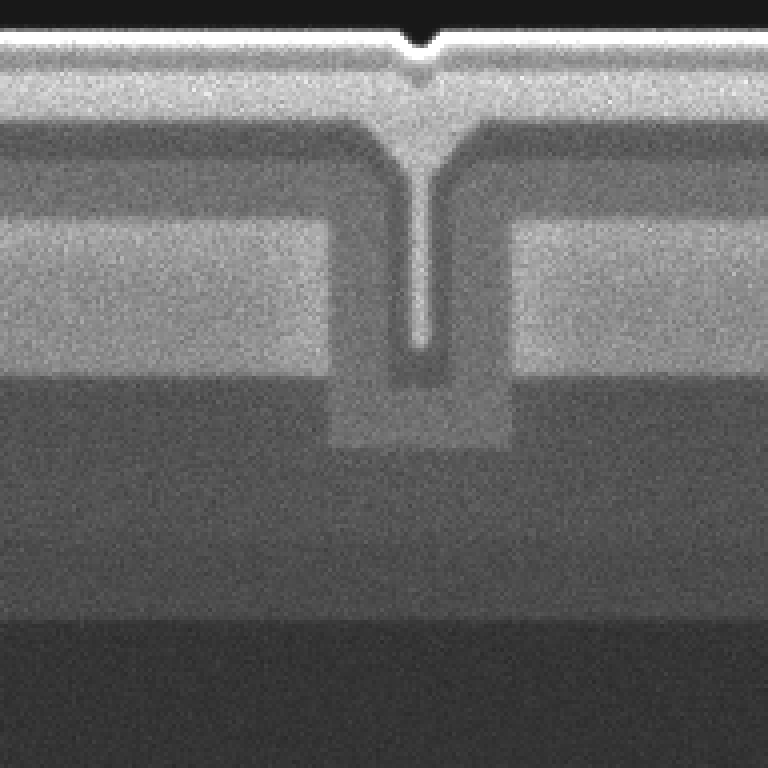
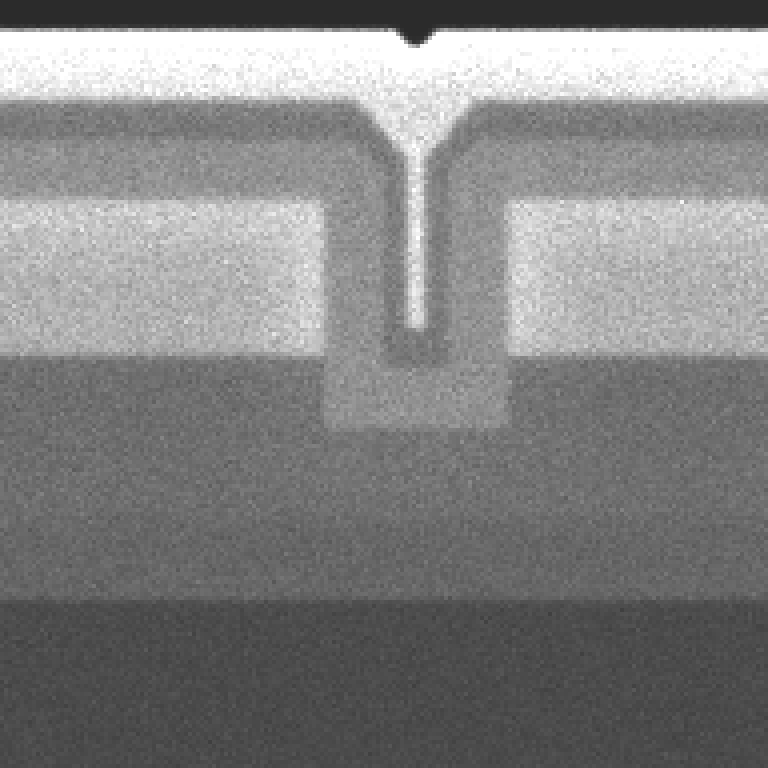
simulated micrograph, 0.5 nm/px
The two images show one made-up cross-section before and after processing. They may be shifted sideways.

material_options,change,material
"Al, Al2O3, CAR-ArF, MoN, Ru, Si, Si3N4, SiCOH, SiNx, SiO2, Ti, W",removed,Al2O3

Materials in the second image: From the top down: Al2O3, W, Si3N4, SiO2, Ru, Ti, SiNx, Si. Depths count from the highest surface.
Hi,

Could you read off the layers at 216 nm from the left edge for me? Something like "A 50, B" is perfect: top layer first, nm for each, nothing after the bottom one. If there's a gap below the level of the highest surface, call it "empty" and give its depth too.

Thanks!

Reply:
empty 2, Al2O3 10, W 46, Si3N4 110, SiO2 30, Ti 46, SiNx 40, Si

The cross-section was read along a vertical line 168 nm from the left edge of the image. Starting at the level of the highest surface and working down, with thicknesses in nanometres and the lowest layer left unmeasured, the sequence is Al2O3 10, W 24, Si3N4 20, SiO2 144, Ti 46, SiNx 40, Si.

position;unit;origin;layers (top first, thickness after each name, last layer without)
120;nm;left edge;Al2O3 10, W 24, Si3N4 20, SiO2 30, Ru 78, Ti 82, SiNx 40, Si